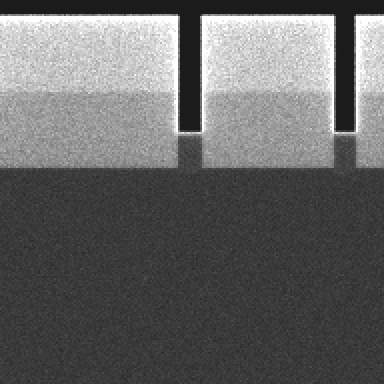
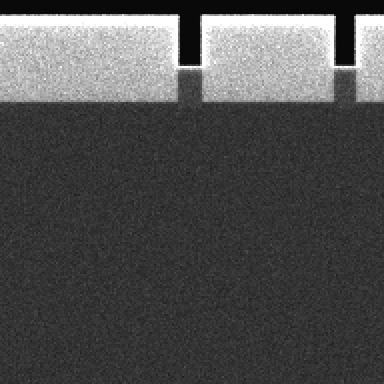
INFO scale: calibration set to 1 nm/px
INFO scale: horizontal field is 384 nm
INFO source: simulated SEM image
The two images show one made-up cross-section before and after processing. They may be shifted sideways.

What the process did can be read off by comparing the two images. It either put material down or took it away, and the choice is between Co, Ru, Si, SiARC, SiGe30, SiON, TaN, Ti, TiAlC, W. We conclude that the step removed W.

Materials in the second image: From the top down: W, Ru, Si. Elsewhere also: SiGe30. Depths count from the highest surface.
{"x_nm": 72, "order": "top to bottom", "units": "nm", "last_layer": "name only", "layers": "W 10, Ru 76, Si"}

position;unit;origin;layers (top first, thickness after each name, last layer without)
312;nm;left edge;W 10, Ru 76, Si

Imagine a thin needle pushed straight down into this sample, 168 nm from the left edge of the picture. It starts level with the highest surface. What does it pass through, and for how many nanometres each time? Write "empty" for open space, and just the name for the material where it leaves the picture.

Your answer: W 10, Ru 76, Si